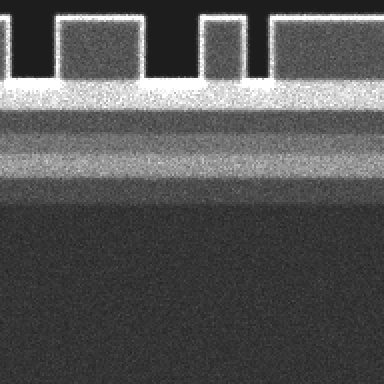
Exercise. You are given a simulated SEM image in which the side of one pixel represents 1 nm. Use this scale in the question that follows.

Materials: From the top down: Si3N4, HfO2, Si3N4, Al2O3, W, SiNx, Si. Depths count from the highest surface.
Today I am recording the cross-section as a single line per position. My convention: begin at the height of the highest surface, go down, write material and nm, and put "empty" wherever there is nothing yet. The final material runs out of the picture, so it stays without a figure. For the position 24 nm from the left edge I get empty 64, HfO2 30, Si3N4 24, Al2O3 20, W 24, SiNx 26, Si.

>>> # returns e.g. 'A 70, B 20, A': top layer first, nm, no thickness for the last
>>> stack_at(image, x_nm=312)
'Si3N4 64, HfO2 30, Si3N4 24, Al2O3 20, W 24, SiNx 26, Si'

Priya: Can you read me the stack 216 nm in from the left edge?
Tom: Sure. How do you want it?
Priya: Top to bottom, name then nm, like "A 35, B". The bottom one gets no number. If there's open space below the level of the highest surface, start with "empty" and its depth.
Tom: Si3N4 64, HfO2 30, Si3N4 24, Al2O3 20, W 24, SiNx 26, Si